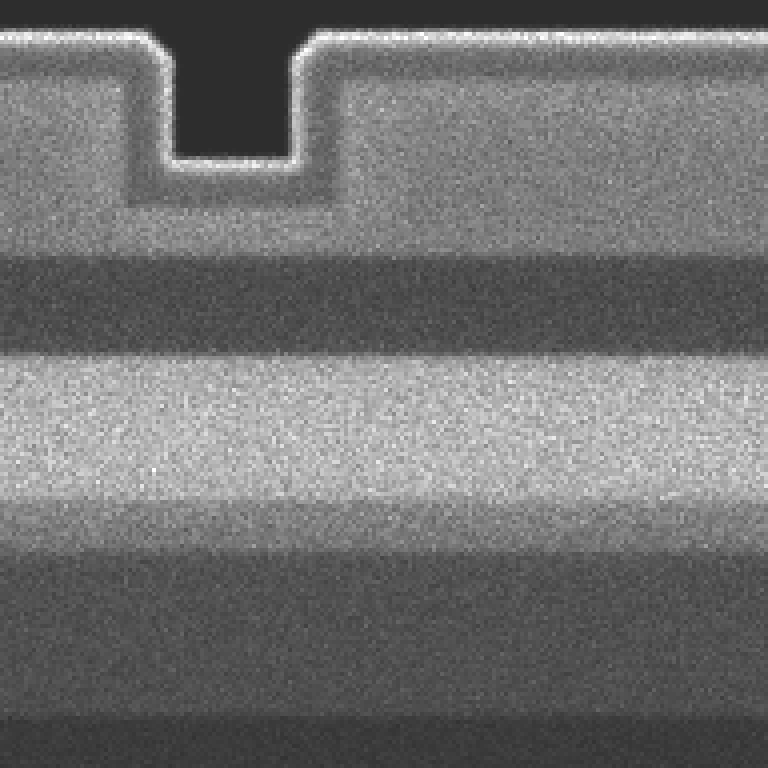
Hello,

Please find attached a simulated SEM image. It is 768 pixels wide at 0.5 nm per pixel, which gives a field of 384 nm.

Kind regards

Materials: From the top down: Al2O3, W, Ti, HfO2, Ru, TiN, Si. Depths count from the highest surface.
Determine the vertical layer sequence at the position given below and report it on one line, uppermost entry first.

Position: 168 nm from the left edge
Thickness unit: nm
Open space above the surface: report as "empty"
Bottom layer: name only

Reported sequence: Al2O3 88, W 24, Ti 50, HfO2 72, Ru 26, TiN 82, Si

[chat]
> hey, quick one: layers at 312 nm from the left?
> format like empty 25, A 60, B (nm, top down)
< Al2O3 24, W 88, Ti 50, HfO2 72, Ru 26, TiN 82, Si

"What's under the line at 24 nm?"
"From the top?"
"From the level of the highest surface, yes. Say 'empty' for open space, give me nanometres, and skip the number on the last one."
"Al2O3 24, W 88, Ti 50, HfO2 72, Ru 26, TiN 82, Si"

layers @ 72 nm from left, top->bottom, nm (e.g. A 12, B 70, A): Al2O3 88, W 24, Ti 50, HfO2 72, Ru 26, TiN 82, Si